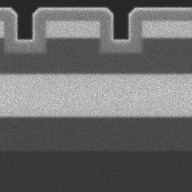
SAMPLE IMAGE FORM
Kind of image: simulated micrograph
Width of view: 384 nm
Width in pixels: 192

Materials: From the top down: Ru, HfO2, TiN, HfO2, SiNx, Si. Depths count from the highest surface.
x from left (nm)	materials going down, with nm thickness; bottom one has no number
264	empty 6, Ru 84, TiN 42, HfO2 86, SiNx 68, Si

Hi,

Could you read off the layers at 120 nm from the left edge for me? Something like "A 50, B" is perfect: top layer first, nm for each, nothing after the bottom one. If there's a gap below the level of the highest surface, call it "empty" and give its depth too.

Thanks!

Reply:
Ru 26, HfO2 34, TiN 72, HfO2 86, SiNx 68, Si